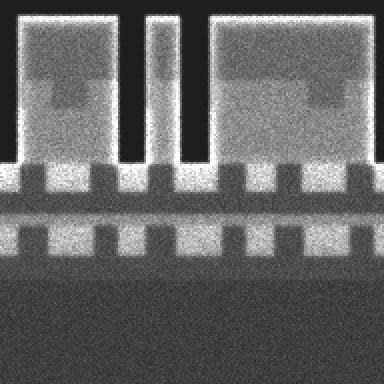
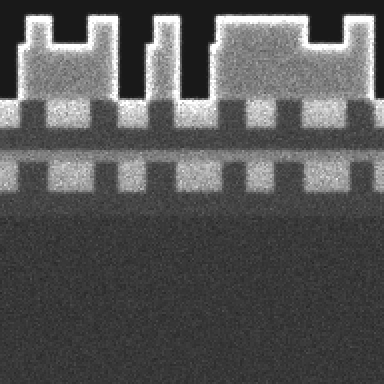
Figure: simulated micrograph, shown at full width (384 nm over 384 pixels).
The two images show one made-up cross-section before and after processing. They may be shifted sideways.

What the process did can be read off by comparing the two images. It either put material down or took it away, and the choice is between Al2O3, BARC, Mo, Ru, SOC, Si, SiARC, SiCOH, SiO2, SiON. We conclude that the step removed SOC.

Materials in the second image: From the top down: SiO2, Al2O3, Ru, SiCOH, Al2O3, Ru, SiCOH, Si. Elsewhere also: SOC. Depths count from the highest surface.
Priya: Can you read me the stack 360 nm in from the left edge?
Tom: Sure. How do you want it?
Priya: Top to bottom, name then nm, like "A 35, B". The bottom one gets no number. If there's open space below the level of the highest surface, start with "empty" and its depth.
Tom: SiO2 76, Al2O3 8, SiCOH 50, Al2O3 12, SiCOH 54, Si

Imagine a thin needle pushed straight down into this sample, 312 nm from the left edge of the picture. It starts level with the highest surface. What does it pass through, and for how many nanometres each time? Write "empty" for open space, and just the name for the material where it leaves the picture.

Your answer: empty 28, SiO2 48, Al2O3 8, Ru 28, SiCOH 22, Al2O3 12, Ru 30, SiCOH 24, Si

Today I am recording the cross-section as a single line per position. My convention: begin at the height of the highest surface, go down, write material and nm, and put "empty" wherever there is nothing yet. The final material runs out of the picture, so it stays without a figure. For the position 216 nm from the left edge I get SiO2 76, Al2O3 8, Ru 28, SiCOH 22, Al2O3 12, Ru 30, SiCOH 24, Si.